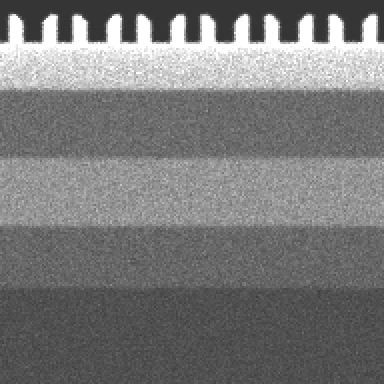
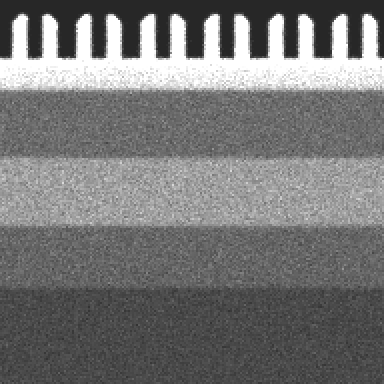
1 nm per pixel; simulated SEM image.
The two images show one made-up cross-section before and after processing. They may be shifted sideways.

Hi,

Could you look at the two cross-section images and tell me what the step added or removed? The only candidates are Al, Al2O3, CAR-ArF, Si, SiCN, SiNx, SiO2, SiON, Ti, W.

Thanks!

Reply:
removed W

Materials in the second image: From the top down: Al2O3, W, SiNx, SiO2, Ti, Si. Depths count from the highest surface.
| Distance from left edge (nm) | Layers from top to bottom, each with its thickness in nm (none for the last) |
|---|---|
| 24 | Al2O3 28, W 46, SiNx 68, SiO2 68, Ti 62, Si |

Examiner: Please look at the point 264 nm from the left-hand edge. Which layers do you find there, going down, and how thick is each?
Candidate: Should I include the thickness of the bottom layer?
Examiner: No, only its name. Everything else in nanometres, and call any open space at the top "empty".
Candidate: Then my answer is empty 44, W 30, SiNx 68, SiO2 68, Ti 62, Si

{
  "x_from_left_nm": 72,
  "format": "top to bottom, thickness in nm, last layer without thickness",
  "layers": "empty 44, W 30, SiNx 68, SiO2 68, Ti 62, Si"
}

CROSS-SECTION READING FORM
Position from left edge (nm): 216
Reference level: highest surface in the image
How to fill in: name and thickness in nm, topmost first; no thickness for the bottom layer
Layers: Al2O3 28, W 46, SiNx 68, SiO2 68, Ti 62, Si